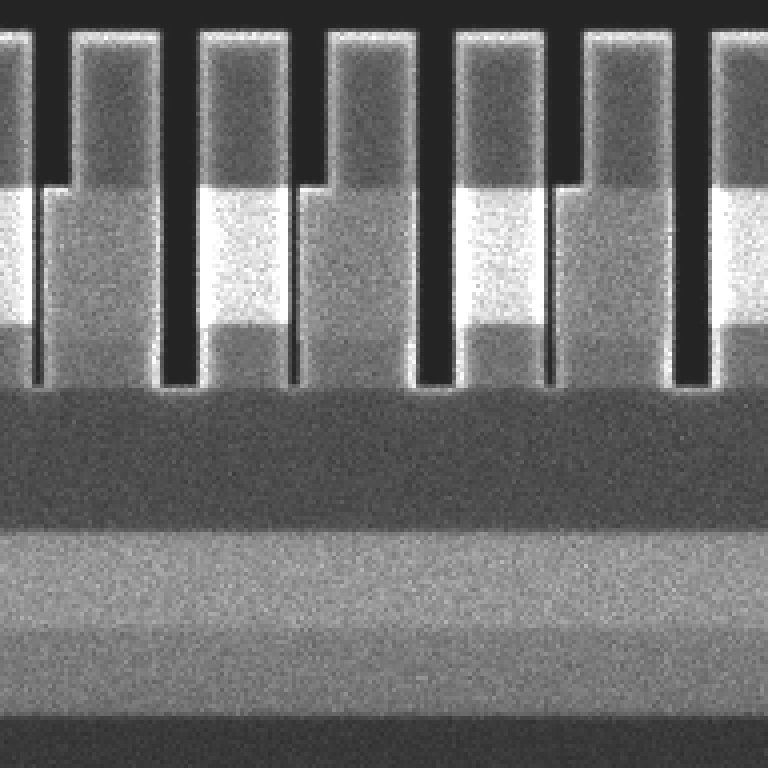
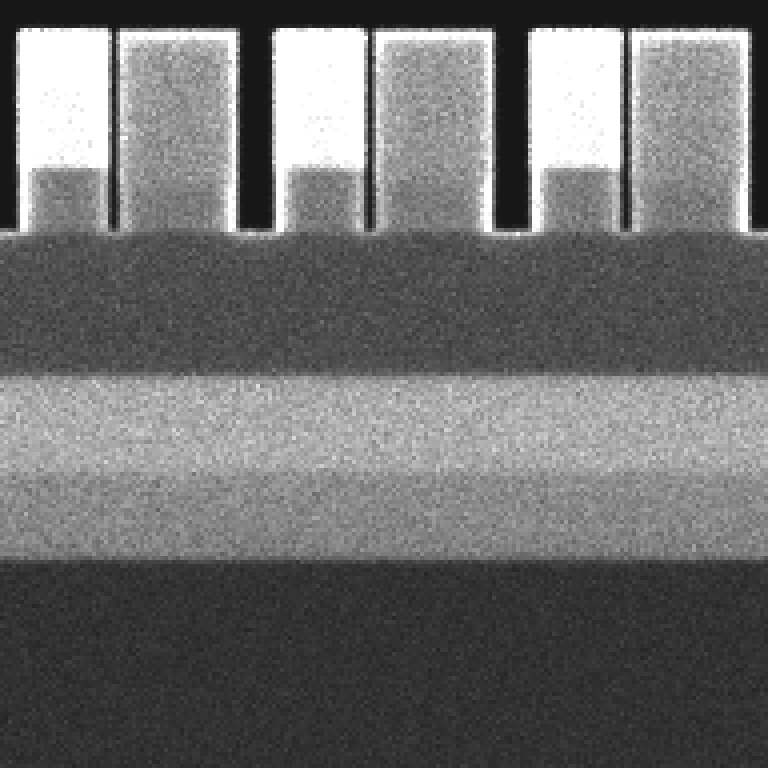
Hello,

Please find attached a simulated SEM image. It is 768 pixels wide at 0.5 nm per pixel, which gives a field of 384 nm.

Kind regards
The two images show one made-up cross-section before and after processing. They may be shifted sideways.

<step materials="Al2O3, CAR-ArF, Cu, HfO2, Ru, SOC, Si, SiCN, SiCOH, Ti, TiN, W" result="removed SOC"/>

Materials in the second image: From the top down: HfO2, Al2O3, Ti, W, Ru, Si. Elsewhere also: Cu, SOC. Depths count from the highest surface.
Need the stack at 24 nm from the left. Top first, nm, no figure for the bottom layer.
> HfO2 68, Al2O3 32, Ti 72, W 48, Ru 44, Si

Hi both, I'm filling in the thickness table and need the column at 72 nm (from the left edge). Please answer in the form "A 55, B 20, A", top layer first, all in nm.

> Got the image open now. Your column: Cu 76, Al2O3 24, Ti 72, W 48, Ru 44, Si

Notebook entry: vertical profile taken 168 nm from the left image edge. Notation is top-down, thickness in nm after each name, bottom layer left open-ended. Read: HfO2 68, Al2O3 32, Ti 72, W 48, Ru 44, Si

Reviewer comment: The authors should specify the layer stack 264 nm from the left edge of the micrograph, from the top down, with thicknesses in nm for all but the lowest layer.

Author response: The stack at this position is empty 100, Ti 72, W 48, Ru 44, Si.